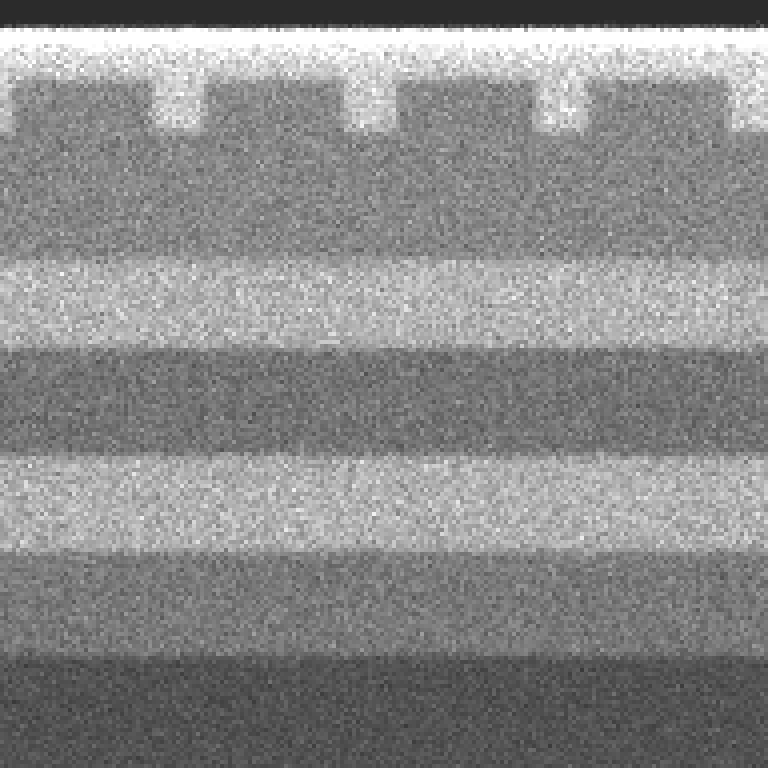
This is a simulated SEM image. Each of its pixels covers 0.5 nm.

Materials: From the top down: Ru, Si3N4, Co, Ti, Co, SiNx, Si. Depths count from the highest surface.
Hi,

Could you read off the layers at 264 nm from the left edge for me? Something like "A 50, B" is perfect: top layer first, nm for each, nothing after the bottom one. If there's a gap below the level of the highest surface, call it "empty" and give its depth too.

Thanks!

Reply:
Ru 24, Si3N4 90, Co 44, Ti 54, Co 48, SiNx 52, Si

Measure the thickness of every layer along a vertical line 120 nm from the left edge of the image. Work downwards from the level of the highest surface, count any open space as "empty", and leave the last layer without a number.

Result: Ru 24, Si3N4 90, Co 44, Ti 54, Co 48, SiNx 52, Si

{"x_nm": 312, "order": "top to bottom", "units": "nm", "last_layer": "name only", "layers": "Ru 24, Si3N4 90, Co 44, Ti 54, Co 48, SiNx 52, Si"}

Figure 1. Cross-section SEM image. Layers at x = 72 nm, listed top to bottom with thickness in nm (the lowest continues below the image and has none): Ru 24, Si3N4 90, Co 44, Ti 54, Co 48, SiNx 52, Si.